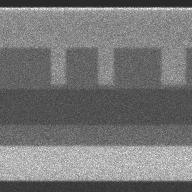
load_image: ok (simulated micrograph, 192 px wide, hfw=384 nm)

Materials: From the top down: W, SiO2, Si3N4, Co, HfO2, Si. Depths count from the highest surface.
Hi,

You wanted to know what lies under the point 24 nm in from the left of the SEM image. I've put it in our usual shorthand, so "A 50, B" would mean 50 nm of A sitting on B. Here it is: W 80, SiO2 82, Si3N4 72, Co 42, HfO2 70, Si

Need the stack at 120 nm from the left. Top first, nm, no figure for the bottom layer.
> W 154, SiO2 8, Si3N4 72, Co 42, HfO2 70, Si